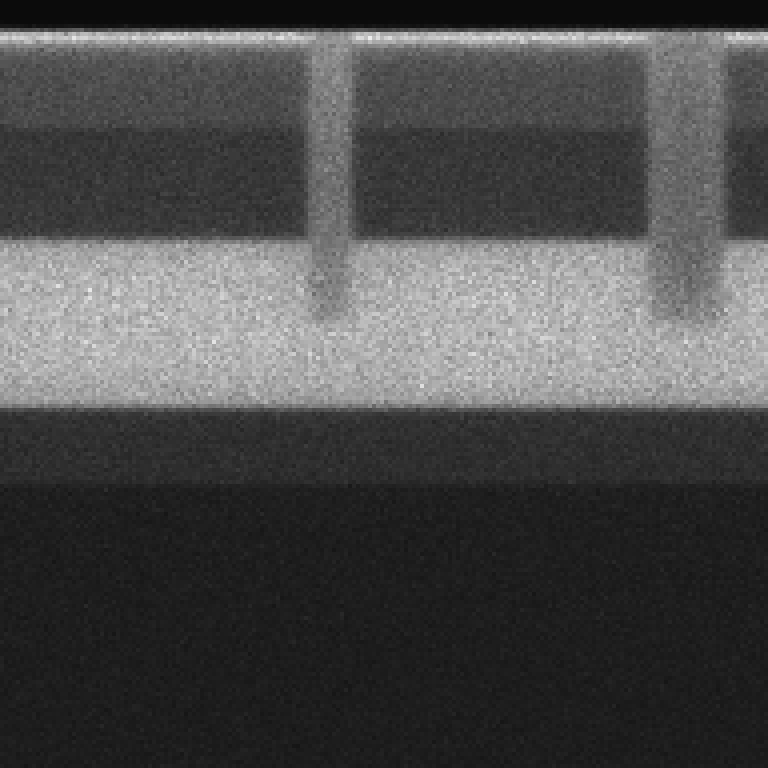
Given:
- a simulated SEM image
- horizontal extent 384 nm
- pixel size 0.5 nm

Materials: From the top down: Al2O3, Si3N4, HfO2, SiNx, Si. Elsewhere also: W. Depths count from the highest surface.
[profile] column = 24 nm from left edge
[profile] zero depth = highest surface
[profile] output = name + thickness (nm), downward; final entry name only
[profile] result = Al2O3 48, Si3N4 56, HfO2 84, SiNx 38, Si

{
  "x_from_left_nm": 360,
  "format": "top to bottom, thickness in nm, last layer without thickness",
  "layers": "W 146, HfO2 42, SiNx 38, Si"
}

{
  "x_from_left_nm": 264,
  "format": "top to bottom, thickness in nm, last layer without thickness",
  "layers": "Al2O3 48, Si3N4 56, HfO2 84, SiNx 38, Si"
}